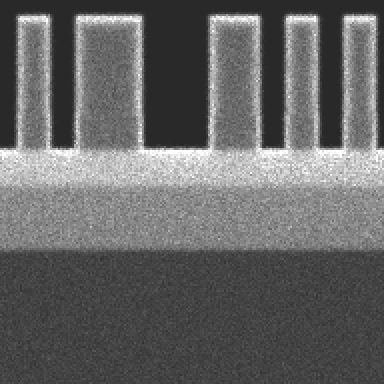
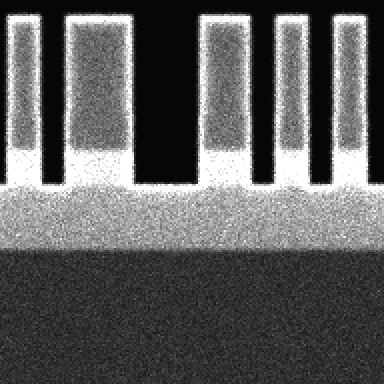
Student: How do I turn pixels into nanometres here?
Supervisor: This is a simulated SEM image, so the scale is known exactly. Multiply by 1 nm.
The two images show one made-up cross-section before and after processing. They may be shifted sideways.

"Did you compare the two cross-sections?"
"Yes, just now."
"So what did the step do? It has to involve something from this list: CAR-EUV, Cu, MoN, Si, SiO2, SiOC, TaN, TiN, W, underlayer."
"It removed W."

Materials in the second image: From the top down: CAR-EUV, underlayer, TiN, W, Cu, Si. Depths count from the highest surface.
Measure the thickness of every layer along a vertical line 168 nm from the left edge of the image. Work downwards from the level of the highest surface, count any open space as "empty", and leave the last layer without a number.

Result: empty 170, Cu 64, Si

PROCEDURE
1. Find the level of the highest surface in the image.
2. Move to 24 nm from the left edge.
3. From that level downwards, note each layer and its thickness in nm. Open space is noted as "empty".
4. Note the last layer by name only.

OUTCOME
CAR-EUV 50, underlayer 48, TiN 36, W 36, Cu 64, Si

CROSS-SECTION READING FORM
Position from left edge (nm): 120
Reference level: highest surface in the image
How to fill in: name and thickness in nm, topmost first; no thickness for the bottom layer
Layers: CAR-EUV 50, underlayer 48, TiN 36, W 36, Cu 64, Si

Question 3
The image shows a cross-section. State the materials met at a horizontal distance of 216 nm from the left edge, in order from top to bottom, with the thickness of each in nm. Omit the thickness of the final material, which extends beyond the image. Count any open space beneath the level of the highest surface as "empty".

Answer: CAR-EUV 50, underlayer 48, TiN 36, W 36, Cu 64, Si